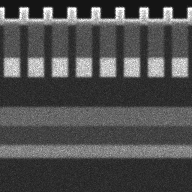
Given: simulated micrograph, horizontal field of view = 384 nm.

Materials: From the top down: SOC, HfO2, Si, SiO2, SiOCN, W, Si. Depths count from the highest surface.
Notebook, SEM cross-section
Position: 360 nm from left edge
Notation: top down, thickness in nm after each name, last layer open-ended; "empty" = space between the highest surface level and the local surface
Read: empty 22, SOC 78, HfO2 38, Si 60, SiO2 38, SiOCN 38, W 26, Si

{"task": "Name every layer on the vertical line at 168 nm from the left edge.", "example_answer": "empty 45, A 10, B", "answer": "empty 22, SOC 78, HfO2 38, Si 60, SiO2 38, SiOCN 38, W 26, Si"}